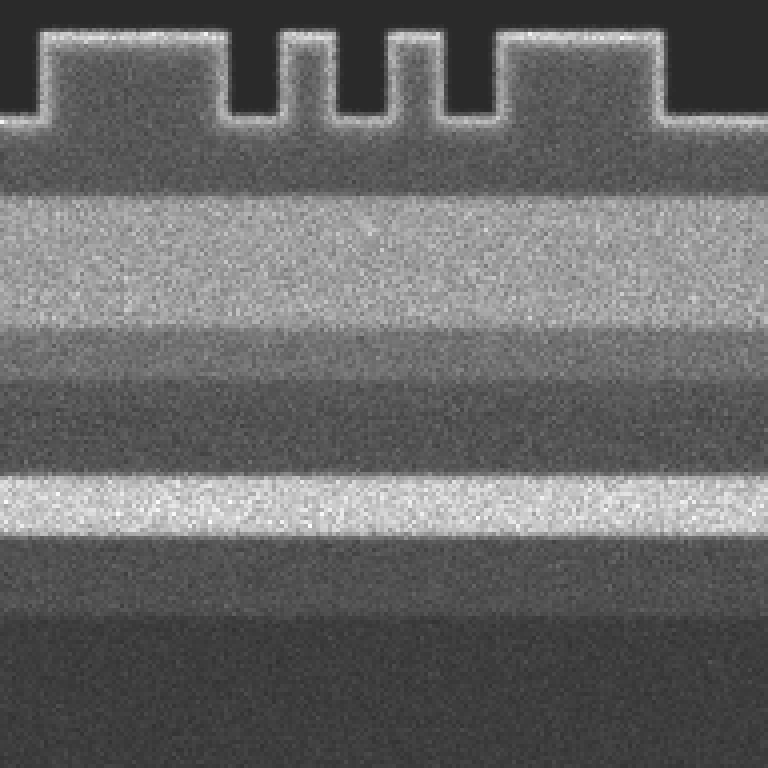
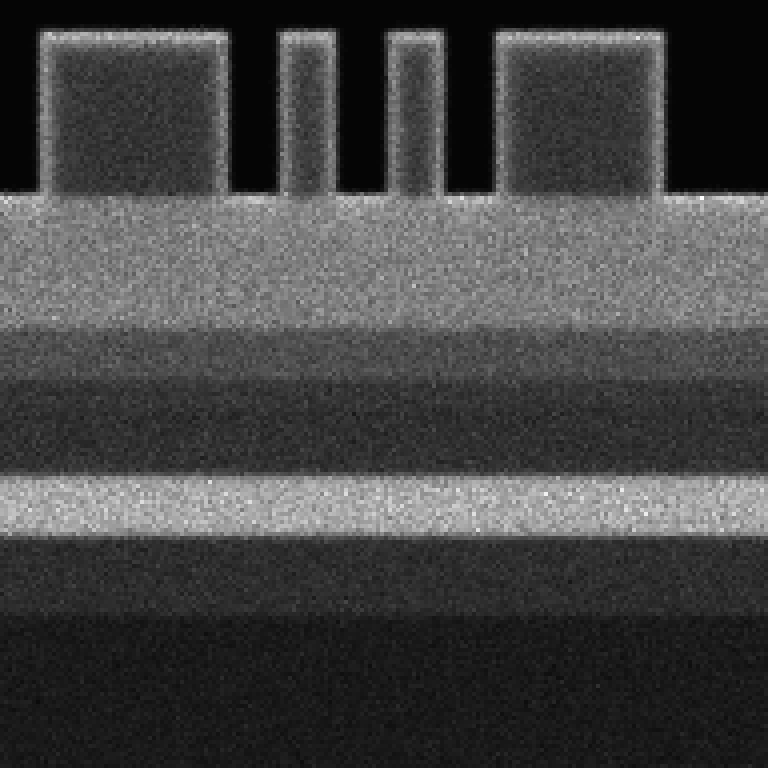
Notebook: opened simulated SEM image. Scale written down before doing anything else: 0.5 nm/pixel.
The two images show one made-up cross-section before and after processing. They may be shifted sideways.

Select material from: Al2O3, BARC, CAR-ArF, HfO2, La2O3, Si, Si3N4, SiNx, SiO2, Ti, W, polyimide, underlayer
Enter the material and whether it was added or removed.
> underlayer / removed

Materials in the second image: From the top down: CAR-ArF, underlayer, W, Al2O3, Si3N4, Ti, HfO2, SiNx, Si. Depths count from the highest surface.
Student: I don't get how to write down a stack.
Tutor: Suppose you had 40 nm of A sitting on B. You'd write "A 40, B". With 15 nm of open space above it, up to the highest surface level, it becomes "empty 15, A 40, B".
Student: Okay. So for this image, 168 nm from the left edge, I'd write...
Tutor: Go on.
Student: empty 82, W 66, Al2O3 26, Si3N4 14, Ti 34, HfO2 30, SiNx 40, Si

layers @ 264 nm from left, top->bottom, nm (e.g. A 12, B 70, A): CAR-ArF 42, underlayer 40, W 66, Al2O3 26, Si3N4 14, Ti 34, HfO2 30, SiNx 40, Si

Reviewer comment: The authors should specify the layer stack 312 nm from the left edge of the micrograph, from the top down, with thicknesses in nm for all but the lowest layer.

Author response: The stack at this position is CAR-ArF 42, underlayer 40, W 66, Al2O3 26, Si3N4 14, Ti 34, HfO2 30, SiNx 40, Si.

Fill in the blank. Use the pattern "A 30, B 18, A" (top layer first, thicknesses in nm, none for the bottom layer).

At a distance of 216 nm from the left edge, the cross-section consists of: CAR-ArF 42, underlayer 40, W 66, Al2O3 26, Si3N4 14, Ti 34, HfO2 30, SiNx 40, Si